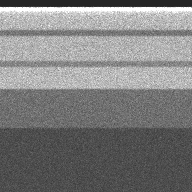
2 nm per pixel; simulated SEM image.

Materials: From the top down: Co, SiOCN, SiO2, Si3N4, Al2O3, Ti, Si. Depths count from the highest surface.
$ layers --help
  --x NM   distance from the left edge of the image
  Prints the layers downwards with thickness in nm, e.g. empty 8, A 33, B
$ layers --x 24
Co 44, SiOCN 12, SiO2 50, Si3N4 12, Al2O3 44, Ti 78, Si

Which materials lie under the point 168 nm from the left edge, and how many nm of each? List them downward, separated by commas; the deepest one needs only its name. Co 44, SiOCN 12, SiO2 50, Si3N4 12, Al2O3 44, Ti 78, Si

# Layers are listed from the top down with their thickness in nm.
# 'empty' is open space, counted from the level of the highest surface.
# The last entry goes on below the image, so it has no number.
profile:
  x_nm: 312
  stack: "Co 44, SiOCN 12, SiO2 50, Si3N4 12, Al2O3 44, Ti 78, Si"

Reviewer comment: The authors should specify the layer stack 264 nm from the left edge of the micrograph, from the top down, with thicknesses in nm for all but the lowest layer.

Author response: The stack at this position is Co 44, SiOCN 12, SiO2 50, Si3N4 12, Al2O3 44, Ti 78, Si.